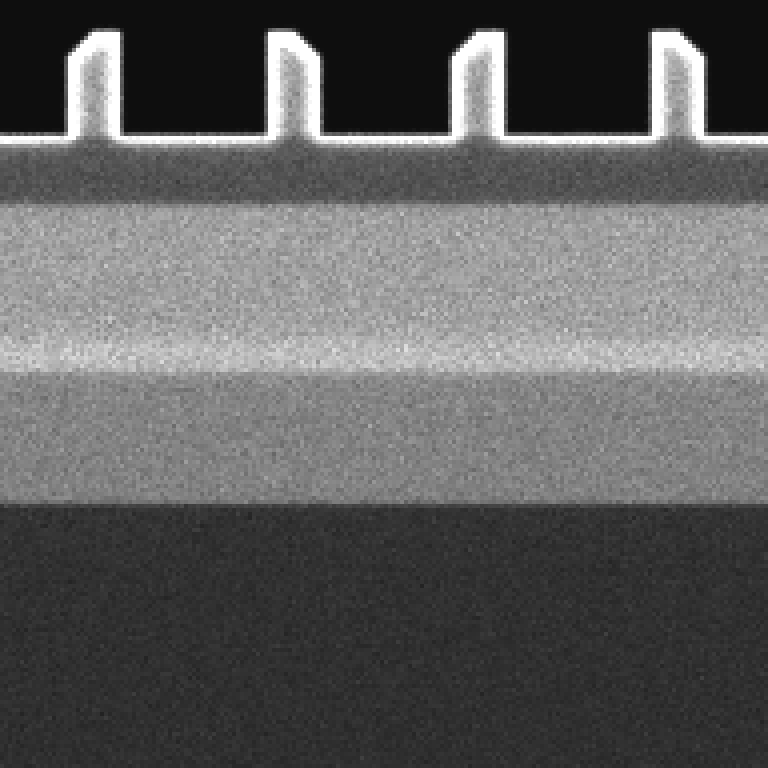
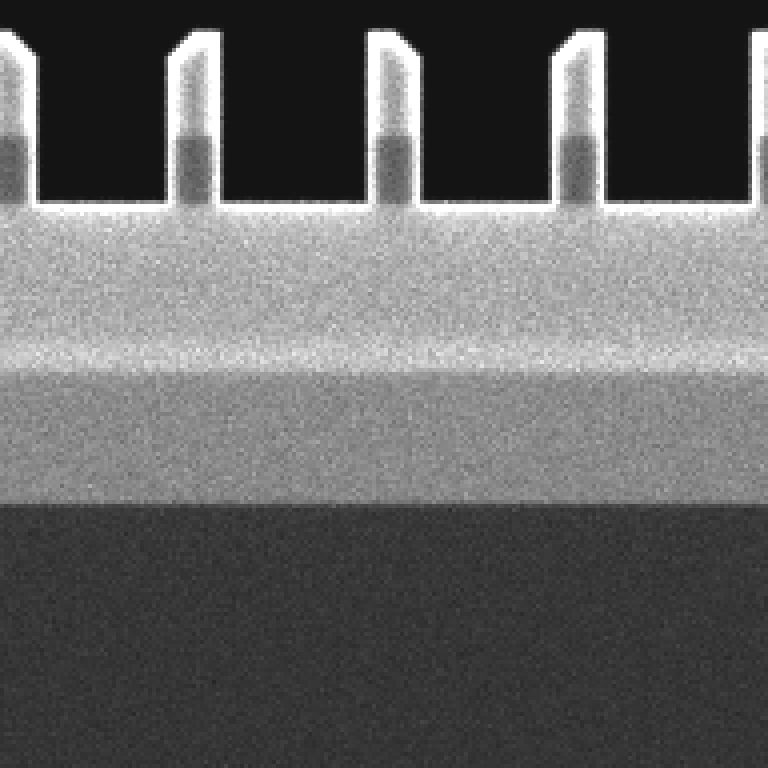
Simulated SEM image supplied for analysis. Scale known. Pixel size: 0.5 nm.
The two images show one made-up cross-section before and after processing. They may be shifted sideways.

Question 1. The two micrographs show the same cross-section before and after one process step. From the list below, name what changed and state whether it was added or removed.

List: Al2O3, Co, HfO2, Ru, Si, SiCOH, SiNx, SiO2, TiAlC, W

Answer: SiNx, removed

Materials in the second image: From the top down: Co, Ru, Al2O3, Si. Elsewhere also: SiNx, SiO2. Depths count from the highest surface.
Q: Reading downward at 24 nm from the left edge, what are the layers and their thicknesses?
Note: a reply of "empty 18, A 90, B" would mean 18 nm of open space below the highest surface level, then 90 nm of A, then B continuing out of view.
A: empty 86, Co 68, Ru 16, Al2O3 66, Si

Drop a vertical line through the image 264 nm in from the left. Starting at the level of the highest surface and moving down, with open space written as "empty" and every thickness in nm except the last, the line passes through empty 86, Co 68, Ru 16, Al2O3 66, Si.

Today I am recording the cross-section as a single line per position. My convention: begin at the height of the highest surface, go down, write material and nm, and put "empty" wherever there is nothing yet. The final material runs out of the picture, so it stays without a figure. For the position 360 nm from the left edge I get empty 86, Co 68, Ru 16, Al2O3 66, Si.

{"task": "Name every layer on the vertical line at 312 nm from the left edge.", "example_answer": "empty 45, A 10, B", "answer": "empty 86, Co 68, Ru 16, Al2O3 66, Si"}